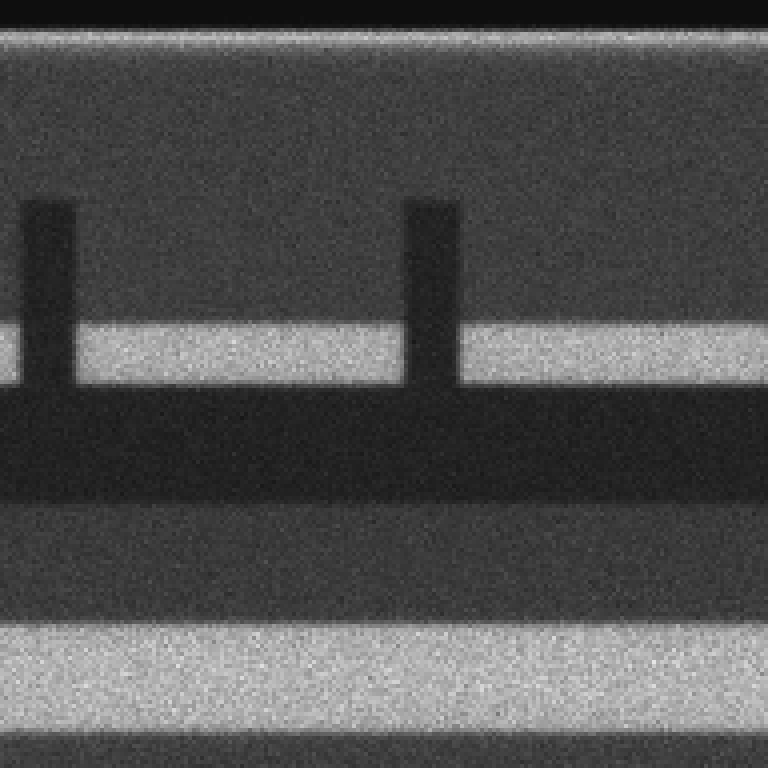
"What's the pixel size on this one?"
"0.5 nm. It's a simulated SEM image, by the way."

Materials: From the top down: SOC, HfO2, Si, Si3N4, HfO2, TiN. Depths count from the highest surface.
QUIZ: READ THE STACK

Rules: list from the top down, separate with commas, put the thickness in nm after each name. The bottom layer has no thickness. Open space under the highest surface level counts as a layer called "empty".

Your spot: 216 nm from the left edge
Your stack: SOC 84, Si 152, Si3N4 60, HfO2 54, TiN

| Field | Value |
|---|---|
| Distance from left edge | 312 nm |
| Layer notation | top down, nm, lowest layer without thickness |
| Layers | SOC 146, HfO2 30, Si 60, Si3N4 60, HfO2 54, TiN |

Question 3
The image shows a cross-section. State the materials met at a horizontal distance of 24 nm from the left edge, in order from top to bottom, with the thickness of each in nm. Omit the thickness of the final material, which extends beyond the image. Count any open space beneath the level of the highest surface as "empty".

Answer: SOC 84, Si 152, Si3N4 60, HfO2 54, TiN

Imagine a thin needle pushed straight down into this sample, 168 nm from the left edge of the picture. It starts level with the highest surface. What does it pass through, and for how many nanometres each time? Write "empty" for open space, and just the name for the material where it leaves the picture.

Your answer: SOC 146, HfO2 30, Si 60, Si3N4 60, HfO2 54, TiN